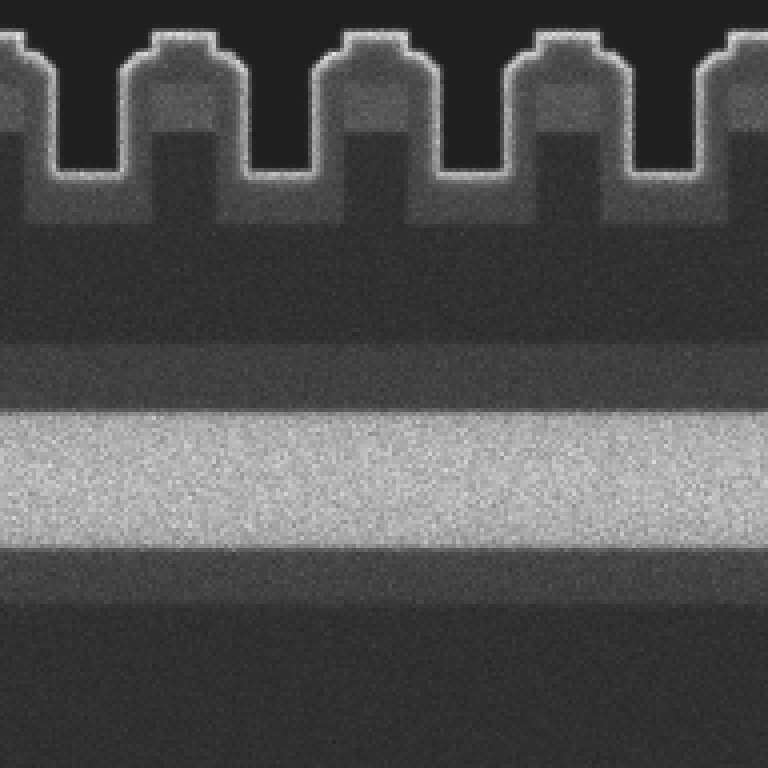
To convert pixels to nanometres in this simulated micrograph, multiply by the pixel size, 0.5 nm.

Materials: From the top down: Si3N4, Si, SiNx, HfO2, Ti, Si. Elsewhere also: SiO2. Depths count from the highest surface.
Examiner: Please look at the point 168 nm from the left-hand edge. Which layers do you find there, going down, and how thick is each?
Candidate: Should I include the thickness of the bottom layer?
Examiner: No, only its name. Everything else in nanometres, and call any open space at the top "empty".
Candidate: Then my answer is empty 10, Si3N4 86, Si 60, SiNx 34, HfO2 68, Ti 28, Si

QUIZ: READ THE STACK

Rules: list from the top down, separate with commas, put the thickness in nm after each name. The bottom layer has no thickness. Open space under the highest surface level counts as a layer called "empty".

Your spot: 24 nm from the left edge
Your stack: empty 16, Si3N4 80, Si 60, SiNx 34, HfO2 68, Ti 28, Si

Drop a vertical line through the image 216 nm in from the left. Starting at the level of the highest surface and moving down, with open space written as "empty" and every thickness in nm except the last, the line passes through empty 16, Si3N4 80, Si 60, SiNx 34, HfO2 68, Ti 28, Si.